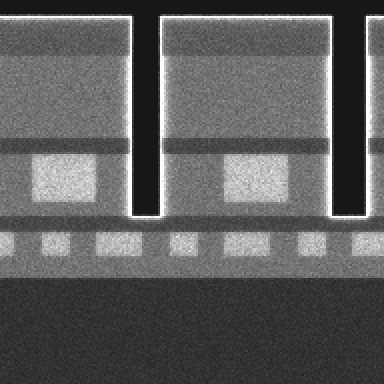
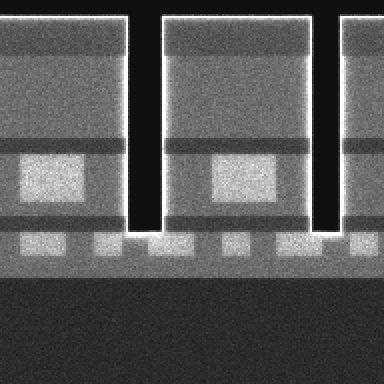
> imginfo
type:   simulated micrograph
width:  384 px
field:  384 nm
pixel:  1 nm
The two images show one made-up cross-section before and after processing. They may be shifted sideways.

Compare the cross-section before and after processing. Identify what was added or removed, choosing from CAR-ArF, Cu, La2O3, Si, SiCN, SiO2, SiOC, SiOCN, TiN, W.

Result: SiCN removed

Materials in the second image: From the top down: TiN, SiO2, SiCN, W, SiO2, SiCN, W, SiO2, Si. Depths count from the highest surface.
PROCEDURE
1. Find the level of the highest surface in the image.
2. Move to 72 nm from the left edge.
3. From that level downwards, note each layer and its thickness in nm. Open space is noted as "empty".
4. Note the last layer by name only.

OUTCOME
TiN 40, SiO2 82, SiCN 16, W 48, SiO2 14, SiCN 16, SiO2 46, Si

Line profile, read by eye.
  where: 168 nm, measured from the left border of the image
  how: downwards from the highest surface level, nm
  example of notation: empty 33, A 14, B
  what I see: TiN 40, SiO2 82, SiCN 16, SiO2 62, SiCN 16, W 24, SiO2 22, Si